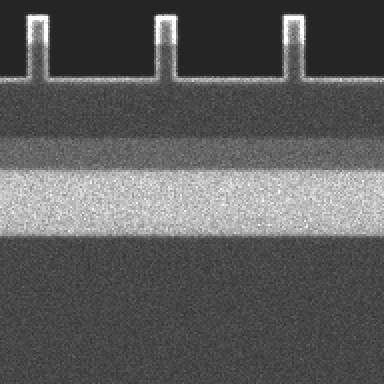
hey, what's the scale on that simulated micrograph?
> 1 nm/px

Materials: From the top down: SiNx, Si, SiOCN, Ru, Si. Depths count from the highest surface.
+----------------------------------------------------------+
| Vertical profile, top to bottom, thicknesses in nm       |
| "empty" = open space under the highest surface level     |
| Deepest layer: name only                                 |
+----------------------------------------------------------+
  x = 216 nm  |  empty 62, Si 60, SiOCN 32, Ru 66, Si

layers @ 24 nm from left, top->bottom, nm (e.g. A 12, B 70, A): empty 62, Si 60, SiOCN 32, Ru 66, Si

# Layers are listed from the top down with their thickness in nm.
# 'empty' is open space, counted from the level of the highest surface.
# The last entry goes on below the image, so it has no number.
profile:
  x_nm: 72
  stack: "empty 62, Si 60, SiOCN 32, Ru 66, Si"